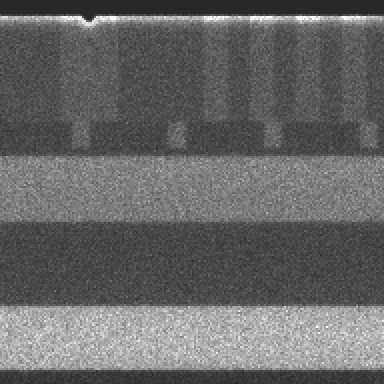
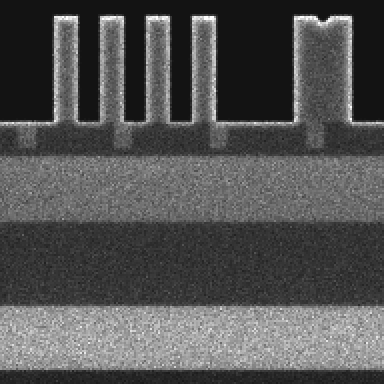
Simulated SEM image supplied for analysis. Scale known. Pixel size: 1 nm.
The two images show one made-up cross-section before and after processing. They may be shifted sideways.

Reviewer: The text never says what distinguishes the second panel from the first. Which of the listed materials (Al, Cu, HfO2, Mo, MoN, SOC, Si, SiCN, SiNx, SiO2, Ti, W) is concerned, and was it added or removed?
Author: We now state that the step removed SOC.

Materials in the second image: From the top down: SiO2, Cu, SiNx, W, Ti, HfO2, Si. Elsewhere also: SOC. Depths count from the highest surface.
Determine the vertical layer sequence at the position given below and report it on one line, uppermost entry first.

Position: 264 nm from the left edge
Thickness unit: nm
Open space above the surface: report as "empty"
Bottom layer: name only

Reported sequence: empty 106, SiNx 34, W 66, Ti 84, HfO2 64, Si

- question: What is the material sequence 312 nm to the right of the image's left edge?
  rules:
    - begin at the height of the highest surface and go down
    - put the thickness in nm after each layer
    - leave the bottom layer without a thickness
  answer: SiO2 106, Cu 26, SiNx 8, W 66, Ti 84, HfO2 64, Si